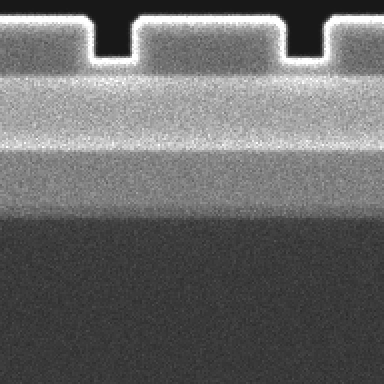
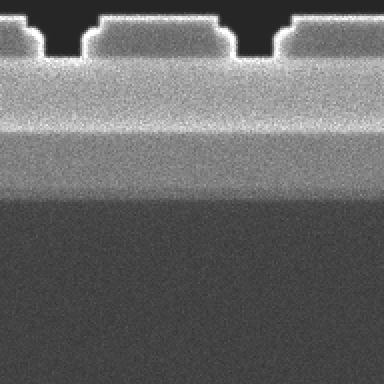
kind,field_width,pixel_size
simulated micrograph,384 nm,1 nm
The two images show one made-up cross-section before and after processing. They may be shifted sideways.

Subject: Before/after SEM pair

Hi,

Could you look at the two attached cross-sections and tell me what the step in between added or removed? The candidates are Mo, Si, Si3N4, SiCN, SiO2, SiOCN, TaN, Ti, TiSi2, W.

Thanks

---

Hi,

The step removed SiO2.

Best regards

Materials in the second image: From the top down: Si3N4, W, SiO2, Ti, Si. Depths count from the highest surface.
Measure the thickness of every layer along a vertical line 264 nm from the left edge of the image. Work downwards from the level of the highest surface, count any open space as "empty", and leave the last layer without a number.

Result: empty 42, W 74, SiO2 56, Ti 12, Si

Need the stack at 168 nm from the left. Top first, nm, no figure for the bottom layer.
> Si3N4 42, W 74, SiO2 56, Ti 12, Si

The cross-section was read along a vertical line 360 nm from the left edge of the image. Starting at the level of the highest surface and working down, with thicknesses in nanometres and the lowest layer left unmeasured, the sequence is Si3N4 42, W 74, SiO2 56, Ti 12, Si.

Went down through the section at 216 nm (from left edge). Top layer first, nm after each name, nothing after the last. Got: Si3N4 42, W 74, SiO2 56, Ti 12, Si